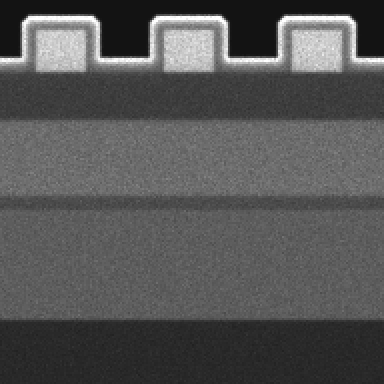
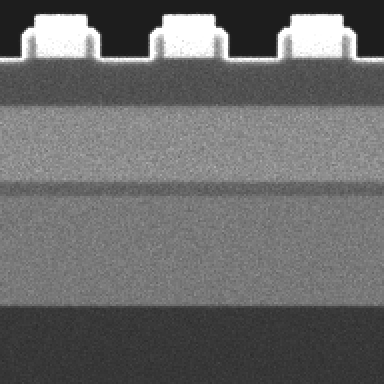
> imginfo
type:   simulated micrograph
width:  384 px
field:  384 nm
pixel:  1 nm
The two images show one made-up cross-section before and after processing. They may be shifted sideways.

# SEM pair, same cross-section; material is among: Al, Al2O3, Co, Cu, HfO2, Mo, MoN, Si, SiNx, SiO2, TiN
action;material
removed;SiO2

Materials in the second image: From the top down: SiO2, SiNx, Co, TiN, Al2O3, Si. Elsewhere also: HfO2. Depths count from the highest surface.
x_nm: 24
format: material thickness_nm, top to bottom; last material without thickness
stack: empty 16, SiO2 26, SiNx 48, Co 76, TiN 14, Al2O3 110, Si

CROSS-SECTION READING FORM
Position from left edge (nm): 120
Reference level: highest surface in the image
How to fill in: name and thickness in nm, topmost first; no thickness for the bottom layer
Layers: empty 42, SiNx 48, Co 76, TiN 14, Al2O3 110, Si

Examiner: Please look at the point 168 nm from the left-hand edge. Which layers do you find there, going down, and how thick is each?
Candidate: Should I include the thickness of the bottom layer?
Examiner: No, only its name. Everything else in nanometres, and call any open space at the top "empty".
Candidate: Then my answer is HfO2 42, SiNx 48, Co 76, TiN 14, Al2O3 110, Si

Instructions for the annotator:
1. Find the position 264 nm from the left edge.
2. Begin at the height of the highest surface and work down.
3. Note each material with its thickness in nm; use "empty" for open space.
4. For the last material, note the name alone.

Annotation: empty 42, SiNx 48, Co 76, TiN 14, Al2O3 110, Si